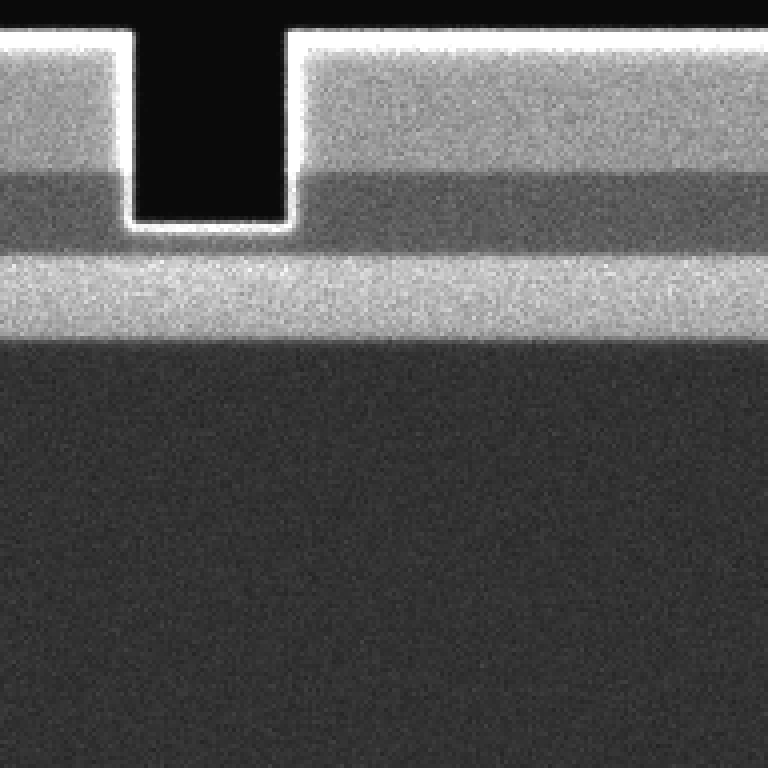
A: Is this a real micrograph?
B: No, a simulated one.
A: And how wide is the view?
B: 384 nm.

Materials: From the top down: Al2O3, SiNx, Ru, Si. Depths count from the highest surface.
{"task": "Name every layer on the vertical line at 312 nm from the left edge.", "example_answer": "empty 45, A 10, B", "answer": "Al2O3 70, SiNx 42, Ru 42, Si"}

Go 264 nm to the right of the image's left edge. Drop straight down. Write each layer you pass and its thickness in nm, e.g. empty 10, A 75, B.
Al2O3 70, SiNx 42, Ru 42, Si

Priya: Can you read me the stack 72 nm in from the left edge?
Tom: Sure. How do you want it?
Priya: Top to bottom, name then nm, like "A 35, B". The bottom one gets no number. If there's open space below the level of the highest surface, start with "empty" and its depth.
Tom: empty 96, SiNx 16, Ru 42, Si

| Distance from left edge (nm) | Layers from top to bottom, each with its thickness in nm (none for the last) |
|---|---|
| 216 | Al2O3 70, SiNx 42, Ru 42, Si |